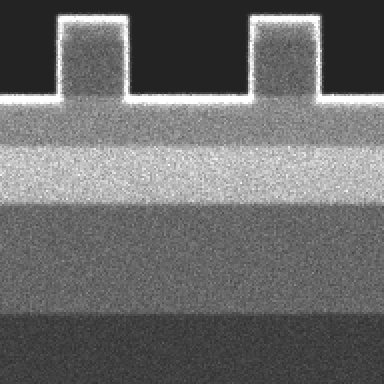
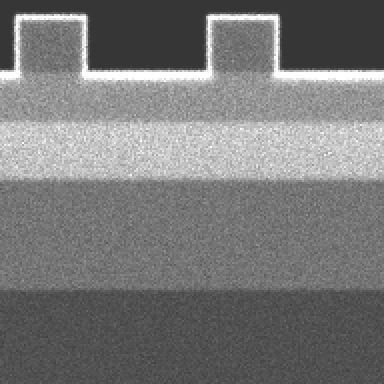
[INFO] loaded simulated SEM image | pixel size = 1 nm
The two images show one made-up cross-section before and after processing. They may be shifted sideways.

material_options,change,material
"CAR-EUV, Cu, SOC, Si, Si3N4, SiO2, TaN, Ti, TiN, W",removed,SOC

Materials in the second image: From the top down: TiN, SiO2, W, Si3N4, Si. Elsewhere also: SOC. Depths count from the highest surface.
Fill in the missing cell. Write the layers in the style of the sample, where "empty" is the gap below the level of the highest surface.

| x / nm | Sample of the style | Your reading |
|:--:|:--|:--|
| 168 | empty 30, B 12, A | empty 56, SiO2 50, W 58, Si3N4 110, Si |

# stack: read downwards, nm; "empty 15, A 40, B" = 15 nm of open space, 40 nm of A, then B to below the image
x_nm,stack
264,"TiN 56, SiO2 50, W 58, Si3N4 110, Si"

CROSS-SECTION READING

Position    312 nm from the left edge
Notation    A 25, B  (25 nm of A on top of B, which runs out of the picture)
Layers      empty 56, SiO2 50, W 58, Si3N4 110, Si